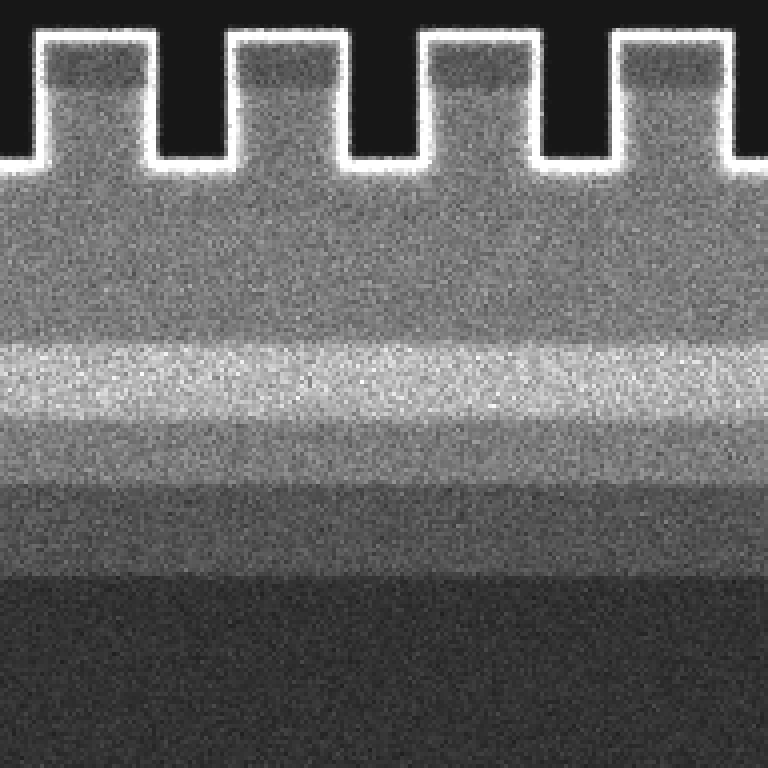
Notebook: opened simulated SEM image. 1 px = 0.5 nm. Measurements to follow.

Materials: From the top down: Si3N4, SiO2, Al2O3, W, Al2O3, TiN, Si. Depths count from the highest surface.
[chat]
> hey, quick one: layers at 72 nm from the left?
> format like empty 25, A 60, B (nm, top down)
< Si3N4 28, SiO2 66, Al2O3 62, W 38, Al2O3 32, TiN 46, Si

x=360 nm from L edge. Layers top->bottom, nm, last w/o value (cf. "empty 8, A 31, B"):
Si3N4 28, SiO2 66, Al2O3 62, W 38, Al2O3 32, TiN 46, Si